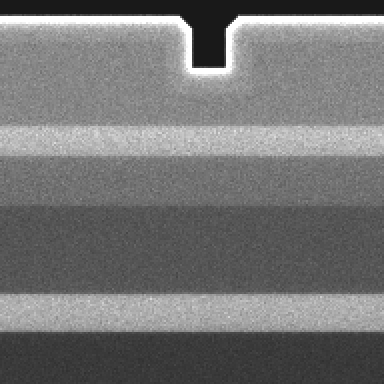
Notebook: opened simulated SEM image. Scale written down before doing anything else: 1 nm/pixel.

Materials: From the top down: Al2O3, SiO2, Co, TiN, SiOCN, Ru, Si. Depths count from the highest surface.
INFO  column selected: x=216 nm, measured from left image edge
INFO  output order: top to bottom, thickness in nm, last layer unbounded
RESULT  empty 52, Al2O3 26, SiO2 32, Co 30, TiN 50, SiOCN 88, Ru 38, Si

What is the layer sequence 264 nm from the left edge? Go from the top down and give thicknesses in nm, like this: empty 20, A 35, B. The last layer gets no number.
Al2O3 26, SiO2 84, Co 30, TiN 50, SiOCN 88, Ru 38, Si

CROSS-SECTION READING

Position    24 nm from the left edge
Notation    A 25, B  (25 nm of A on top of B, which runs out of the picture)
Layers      Al2O3 26, SiO2 84, Co 30, TiN 50, SiOCN 88, Ru 38, Si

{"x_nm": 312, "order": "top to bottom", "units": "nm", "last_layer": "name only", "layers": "Al2O3 26, SiO2 84, Co 30, TiN 50, SiOCN 88, Ru 38, Si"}